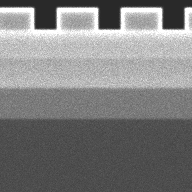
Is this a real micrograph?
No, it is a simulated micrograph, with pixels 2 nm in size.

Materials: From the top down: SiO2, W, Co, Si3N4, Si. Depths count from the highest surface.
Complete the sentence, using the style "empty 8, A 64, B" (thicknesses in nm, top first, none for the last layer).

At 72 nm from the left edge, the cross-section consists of empty 44, W 56, Co 60, Si3N4 62, Si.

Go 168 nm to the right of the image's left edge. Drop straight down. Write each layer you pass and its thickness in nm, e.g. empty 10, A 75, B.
SiO2 44, W 56, Co 60, Si3N4 62, Si